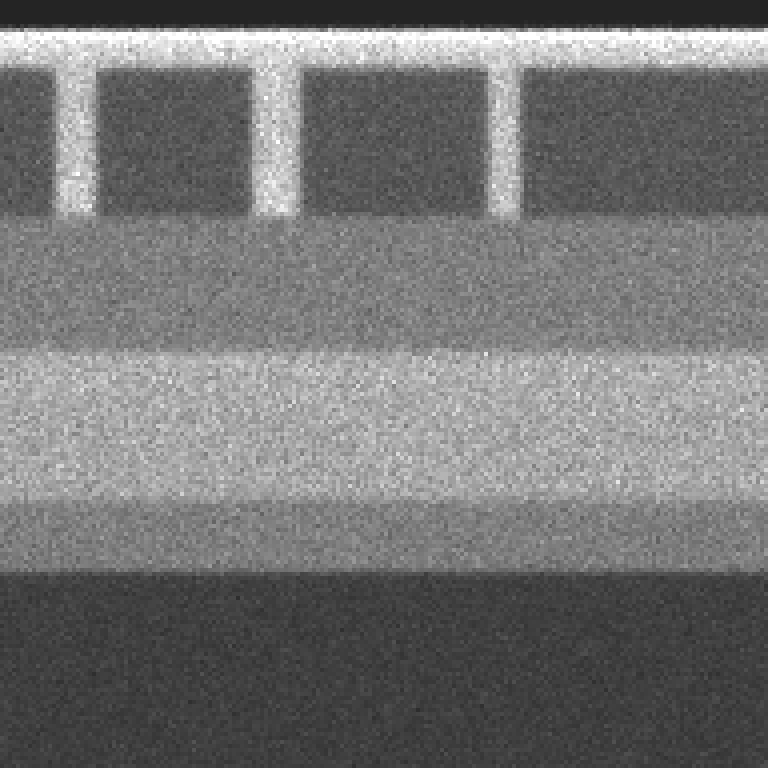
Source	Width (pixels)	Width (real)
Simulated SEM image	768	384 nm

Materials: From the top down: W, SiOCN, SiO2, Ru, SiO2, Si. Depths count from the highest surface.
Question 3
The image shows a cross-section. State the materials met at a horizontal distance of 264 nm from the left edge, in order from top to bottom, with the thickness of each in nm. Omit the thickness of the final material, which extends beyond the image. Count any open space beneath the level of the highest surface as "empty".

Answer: W 18, SiOCN 74, SiO2 68, Ru 74, SiO2 36, Si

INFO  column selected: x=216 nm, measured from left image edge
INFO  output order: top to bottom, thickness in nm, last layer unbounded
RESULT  W 18, SiOCN 74, SiO2 68, Ru 74, SiO2 36, Si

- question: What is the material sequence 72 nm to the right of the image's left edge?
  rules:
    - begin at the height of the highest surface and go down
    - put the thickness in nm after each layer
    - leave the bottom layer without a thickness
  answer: W 18, SiOCN 74, SiO2 68, Ru 74, SiO2 36, Si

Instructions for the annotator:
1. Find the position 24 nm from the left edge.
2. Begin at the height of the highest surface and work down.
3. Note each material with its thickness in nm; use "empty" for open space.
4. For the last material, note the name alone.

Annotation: W 18, SiOCN 74, SiO2 68, Ru 74, SiO2 36, Si